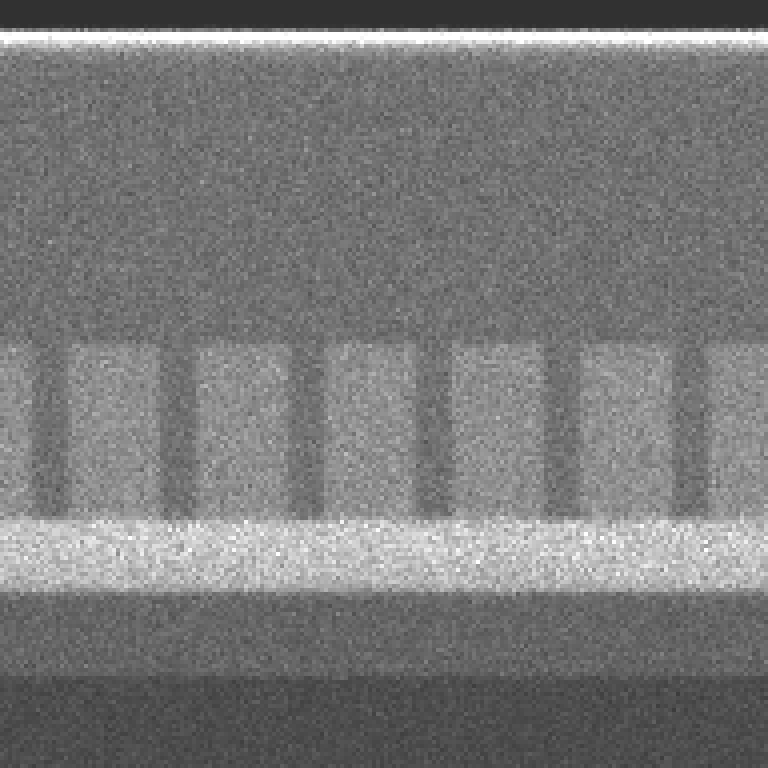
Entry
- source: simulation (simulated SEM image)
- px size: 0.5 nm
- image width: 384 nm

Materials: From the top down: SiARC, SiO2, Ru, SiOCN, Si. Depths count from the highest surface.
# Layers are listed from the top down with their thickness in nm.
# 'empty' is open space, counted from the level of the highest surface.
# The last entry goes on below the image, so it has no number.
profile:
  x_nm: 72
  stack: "SiARC 156, SiO2 88, Ru 36, SiOCN 42, Si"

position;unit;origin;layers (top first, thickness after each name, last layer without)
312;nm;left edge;SiARC 156, SiO2 88, Ru 36, SiOCN 42, Si